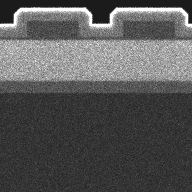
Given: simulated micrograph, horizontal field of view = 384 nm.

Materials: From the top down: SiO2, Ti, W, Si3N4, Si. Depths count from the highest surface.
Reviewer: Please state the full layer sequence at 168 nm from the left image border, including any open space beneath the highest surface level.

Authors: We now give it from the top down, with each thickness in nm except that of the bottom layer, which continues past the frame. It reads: SiO2 58, Ti 6, W 82, Si3N4 24, Si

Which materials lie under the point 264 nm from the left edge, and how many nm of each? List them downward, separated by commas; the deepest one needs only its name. SiO2 26, Ti 38, W 82, Si3N4 24, Si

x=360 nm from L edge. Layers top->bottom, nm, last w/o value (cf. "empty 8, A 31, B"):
SiO2 58, Ti 6, W 82, Si3N4 24, Si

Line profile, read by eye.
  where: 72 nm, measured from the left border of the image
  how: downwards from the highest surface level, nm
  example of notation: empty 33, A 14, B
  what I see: SiO2 26, Ti 38, W 82, Si3N4 24, Si